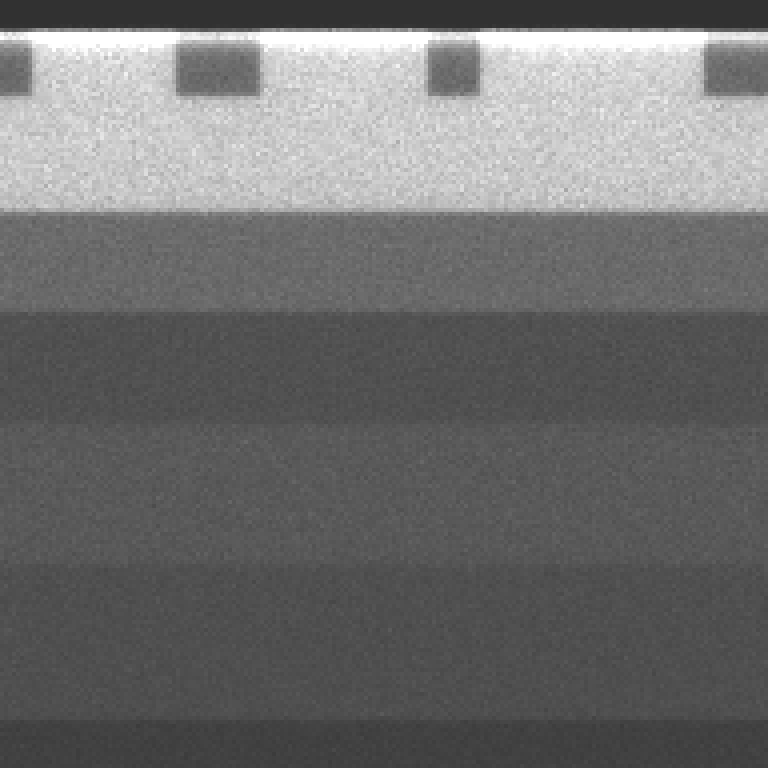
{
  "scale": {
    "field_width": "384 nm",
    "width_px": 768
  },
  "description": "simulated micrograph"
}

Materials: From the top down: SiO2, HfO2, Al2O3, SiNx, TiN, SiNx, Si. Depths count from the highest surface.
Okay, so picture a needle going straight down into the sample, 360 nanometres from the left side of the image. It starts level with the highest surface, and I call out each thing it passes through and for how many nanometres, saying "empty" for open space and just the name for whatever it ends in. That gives SiO2 32, HfO2 58, Al2O3 50, SiNx 56, TiN 70, SiNx 78, Si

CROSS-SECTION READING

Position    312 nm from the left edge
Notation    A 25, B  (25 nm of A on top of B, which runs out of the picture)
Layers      HfO2 90, Al2O3 50, SiNx 56, TiN 70, SiNx 78, Si